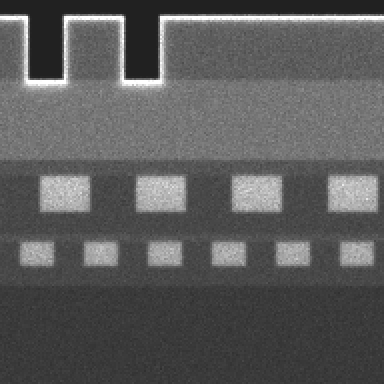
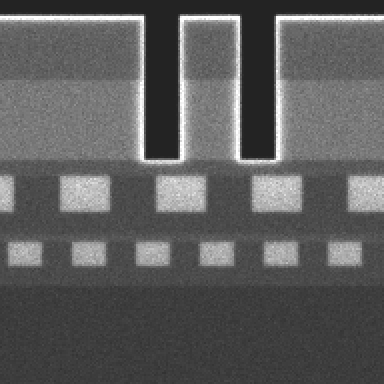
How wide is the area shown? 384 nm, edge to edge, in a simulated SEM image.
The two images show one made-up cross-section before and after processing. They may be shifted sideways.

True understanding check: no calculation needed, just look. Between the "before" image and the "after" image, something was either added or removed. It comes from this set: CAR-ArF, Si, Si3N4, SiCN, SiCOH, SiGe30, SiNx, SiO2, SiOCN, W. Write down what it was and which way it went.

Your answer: SiO2 (removed)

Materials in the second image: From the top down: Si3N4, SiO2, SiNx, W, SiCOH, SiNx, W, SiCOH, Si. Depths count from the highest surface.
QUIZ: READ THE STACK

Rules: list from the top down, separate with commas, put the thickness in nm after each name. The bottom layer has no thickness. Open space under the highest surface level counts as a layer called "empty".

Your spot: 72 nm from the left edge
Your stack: Si3N4 64, SiO2 80, SiNx 16, W 36, SiCOH 22, SiNx 8, W 24, SiCOH 20, Si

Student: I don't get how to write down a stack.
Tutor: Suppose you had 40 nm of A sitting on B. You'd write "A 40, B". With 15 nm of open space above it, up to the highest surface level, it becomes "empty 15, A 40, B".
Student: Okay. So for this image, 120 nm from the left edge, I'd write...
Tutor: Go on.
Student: Si3N4 64, SiO2 80, SiNx 16, SiCOH 58, SiNx 8, SiCOH 44, Si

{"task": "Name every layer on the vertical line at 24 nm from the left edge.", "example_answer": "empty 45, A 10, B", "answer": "Si3N4 64, SiO2 80, SiNx 16, SiCOH 58, SiNx 8, W 24, SiCOH 20, Si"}